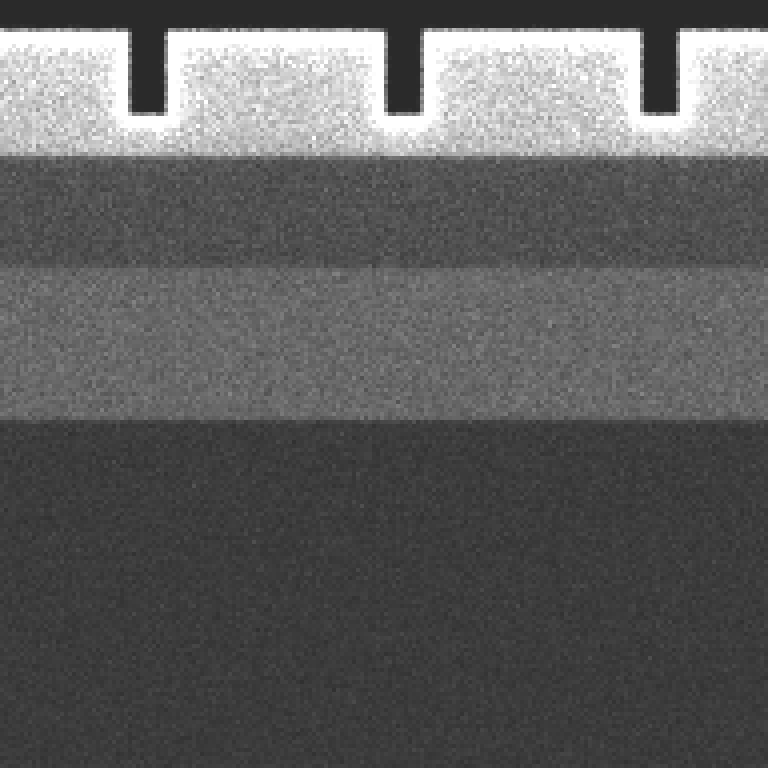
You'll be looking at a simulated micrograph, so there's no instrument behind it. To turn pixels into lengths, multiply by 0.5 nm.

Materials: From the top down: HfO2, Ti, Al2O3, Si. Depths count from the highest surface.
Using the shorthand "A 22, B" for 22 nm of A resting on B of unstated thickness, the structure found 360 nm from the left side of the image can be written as HfO2 62, Ti 56, Al2O3 76, Si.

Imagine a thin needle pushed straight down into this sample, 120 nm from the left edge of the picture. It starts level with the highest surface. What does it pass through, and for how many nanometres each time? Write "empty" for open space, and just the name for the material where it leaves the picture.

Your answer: HfO2 62, Ti 56, Al2O3 76, Si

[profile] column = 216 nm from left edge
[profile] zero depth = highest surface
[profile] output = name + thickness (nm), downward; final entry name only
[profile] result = HfO2 62, Ti 56, Al2O3 76, Si